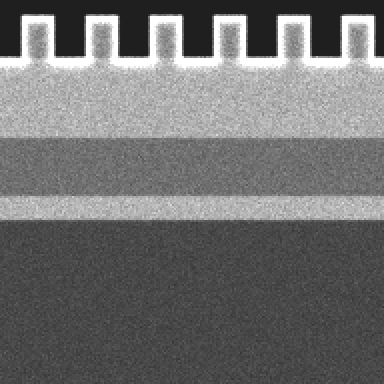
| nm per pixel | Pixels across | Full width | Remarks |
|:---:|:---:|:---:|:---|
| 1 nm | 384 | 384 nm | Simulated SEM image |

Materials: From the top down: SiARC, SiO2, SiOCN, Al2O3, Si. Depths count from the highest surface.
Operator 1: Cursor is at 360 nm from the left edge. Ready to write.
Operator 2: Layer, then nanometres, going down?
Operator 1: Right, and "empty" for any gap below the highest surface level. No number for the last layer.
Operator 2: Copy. SiARC 42, SiO2 80, SiOCN 58, Al2O3 24, Si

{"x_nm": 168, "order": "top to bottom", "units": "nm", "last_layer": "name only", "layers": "SiARC 42, SiO2 80, SiOCN 58, Al2O3 24, Si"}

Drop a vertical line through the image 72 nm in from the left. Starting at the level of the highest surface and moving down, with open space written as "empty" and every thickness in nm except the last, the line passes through empty 42, SiO2 80, SiOCN 58, Al2O3 24, Si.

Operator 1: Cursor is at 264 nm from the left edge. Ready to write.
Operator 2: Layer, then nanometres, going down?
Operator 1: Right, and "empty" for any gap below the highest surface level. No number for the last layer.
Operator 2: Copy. empty 42, SiO2 80, SiOCN 58, Al2O3 24, Si